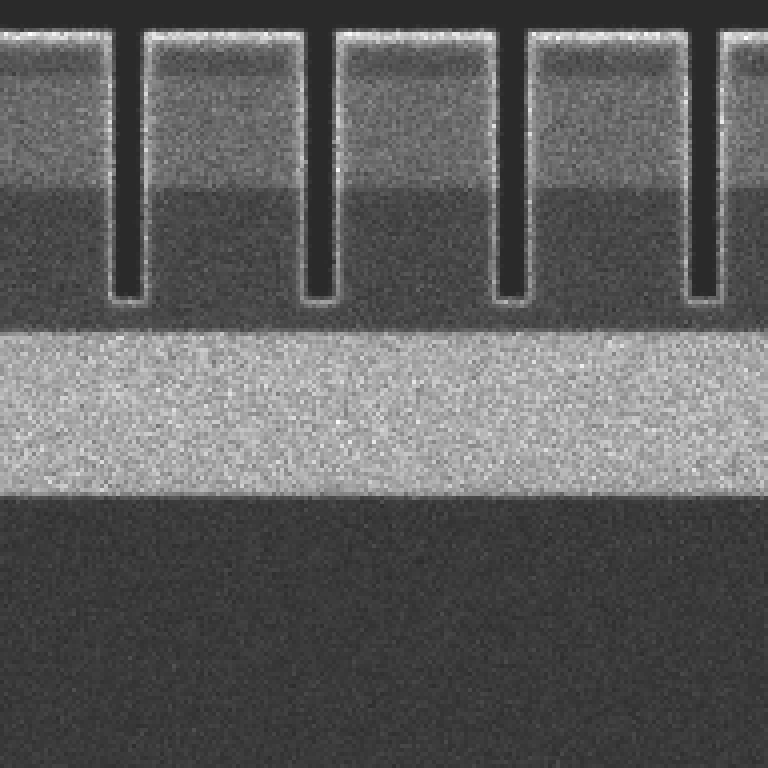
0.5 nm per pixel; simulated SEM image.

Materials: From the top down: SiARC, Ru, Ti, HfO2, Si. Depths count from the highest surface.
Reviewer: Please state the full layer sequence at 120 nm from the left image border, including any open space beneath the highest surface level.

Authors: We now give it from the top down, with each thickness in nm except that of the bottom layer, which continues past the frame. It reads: SiARC 22, Ru 56, Ti 72, HfO2 82, Si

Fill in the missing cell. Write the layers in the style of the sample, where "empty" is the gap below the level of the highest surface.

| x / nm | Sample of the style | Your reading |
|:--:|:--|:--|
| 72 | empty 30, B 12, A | SiARC 22, Ru 56, Ti 72, HfO2 82, Si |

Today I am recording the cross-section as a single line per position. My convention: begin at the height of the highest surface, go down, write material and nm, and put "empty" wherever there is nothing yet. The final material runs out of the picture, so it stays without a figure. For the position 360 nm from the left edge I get SiARC 22, Ru 56, Ti 72, HfO2 82, Si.